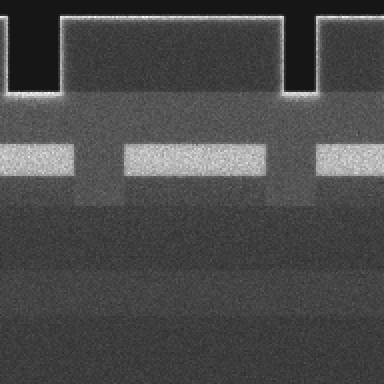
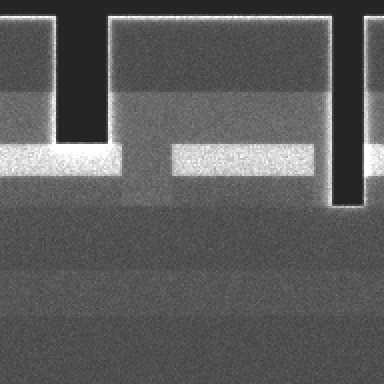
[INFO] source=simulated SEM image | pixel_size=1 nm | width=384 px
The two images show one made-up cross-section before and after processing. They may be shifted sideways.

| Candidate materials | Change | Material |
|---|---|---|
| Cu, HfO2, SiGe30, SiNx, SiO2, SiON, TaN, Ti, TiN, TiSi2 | removed | SiO2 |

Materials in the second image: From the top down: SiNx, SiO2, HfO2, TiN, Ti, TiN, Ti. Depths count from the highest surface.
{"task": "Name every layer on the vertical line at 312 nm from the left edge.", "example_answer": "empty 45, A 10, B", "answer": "SiNx 76, SiO2 52, HfO2 32, TiN 30, Ti 64, TiN 46, Ti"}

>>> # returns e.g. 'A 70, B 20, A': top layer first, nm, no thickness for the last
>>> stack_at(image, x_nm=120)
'SiNx 76, SiO2 52, HfO2 32, TiN 30, Ti 64, TiN 46, Ti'